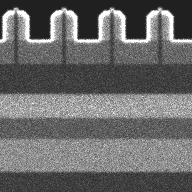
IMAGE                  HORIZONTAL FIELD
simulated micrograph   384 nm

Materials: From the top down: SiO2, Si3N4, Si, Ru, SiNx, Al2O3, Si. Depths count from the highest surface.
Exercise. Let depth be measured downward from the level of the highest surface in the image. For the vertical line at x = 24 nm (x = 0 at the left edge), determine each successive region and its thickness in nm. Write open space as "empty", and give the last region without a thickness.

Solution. empty 6, SiO2 58, Si3N4 48, Si 60, Ru 48, SiNx 42, Al2O3 66, Si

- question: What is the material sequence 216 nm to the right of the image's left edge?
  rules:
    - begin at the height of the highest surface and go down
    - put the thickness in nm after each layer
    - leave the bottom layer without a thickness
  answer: empty 6, SiO2 58, Si3N4 48, Si 60, Ru 48, SiNx 42, Al2O3 66, Si